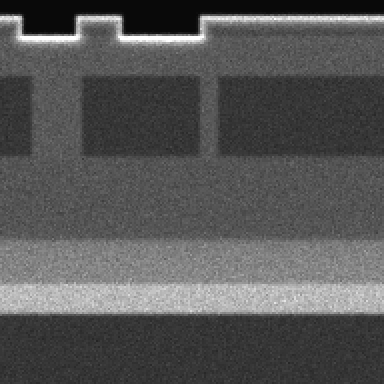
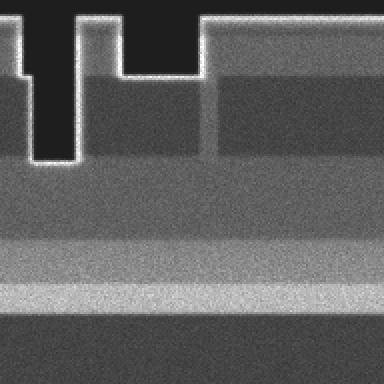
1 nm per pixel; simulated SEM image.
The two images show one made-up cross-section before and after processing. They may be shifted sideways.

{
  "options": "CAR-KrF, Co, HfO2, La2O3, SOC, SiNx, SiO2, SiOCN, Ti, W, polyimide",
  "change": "removed",
  "material": "SiO2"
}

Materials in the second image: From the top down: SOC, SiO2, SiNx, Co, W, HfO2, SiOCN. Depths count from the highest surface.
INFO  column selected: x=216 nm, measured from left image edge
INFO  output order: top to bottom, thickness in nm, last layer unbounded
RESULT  SOC 20, SiO2 126, Co 78, W 44, HfO2 30, SiOCN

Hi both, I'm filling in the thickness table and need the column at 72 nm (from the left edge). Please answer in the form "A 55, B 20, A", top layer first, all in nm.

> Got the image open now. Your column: empty 146, Co 78, W 44, HfO2 30, SiOCN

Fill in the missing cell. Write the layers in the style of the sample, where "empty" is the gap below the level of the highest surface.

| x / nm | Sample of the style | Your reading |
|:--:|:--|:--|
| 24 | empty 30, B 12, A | empty 60, SiNx 80, Co 84, W 44, HfO2 30, SiOCN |